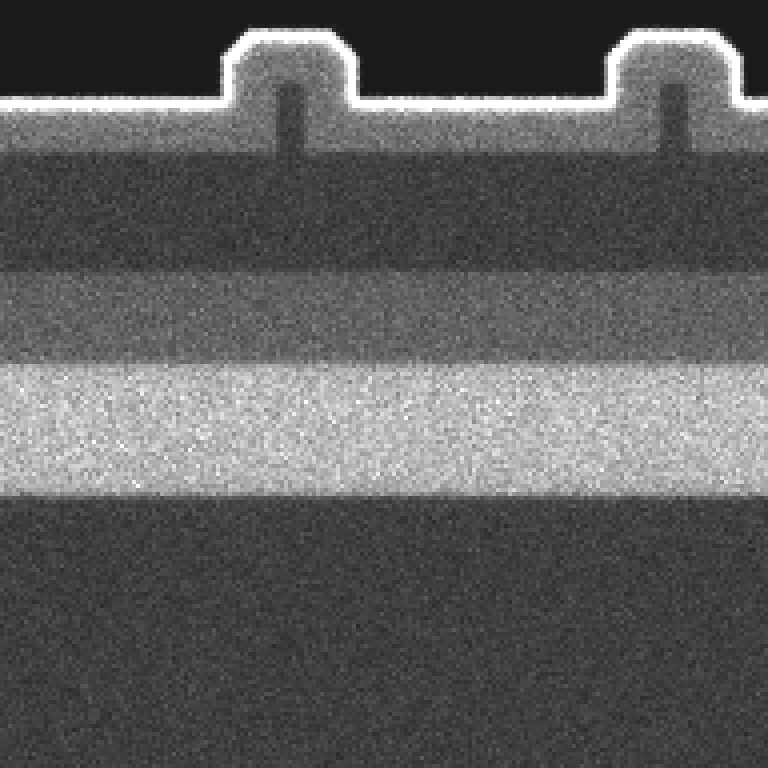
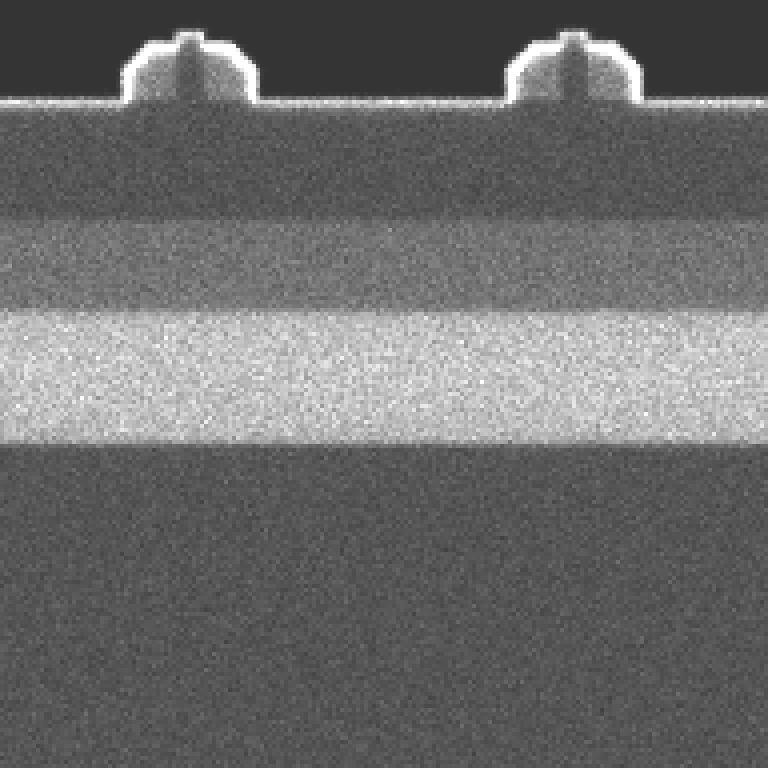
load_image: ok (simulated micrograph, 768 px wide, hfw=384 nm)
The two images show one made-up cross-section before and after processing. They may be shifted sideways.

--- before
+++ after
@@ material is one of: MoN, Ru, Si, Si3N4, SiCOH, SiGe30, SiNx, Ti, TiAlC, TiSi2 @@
Si3N4 removed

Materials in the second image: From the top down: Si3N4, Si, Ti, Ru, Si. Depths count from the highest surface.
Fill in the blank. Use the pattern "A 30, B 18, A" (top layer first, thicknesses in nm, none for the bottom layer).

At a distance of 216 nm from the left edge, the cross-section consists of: empty 34, Si 60, Ti 46, Ru 66, Si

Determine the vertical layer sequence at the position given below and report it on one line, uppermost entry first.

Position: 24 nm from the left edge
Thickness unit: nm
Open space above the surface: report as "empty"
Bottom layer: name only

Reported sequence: empty 34, Si 60, Ti 46, Ru 66, Si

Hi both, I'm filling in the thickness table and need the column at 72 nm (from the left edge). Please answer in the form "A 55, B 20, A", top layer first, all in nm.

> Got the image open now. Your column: empty 8, Si3N4 26, Si 60, Ti 46, Ru 66, Si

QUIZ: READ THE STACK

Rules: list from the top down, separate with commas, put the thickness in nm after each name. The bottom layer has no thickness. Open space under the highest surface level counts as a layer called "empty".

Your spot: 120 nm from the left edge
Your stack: empty 12, Si3N4 22, Si 60, Ti 46, Ru 66, Si